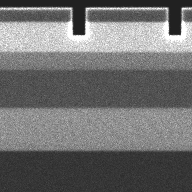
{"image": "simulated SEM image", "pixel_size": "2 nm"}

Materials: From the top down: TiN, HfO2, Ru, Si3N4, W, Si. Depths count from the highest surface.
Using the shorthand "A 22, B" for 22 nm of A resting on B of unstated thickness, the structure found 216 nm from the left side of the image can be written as TiN 28, HfO2 60, Ru 36, Si3N4 76, W 86, Si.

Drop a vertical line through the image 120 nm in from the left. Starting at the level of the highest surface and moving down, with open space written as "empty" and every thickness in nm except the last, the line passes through TiN 28, HfO2 60, Ru 36, Si3N4 76, W 86, Si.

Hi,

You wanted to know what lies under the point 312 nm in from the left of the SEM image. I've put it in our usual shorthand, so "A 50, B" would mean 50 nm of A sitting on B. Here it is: TiN 28, HfO2 60, Ru 36, Si3N4 76, W 86, Si